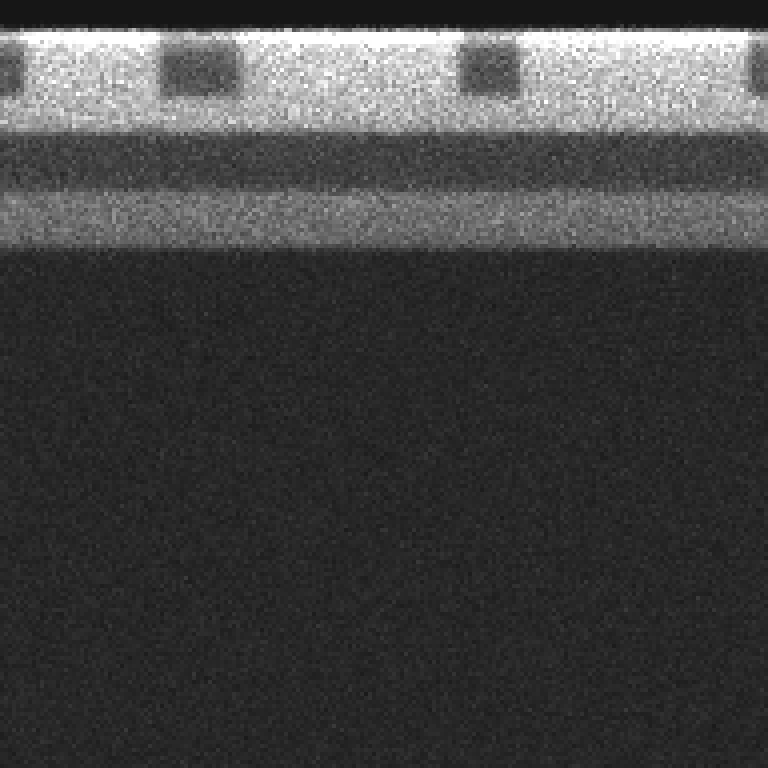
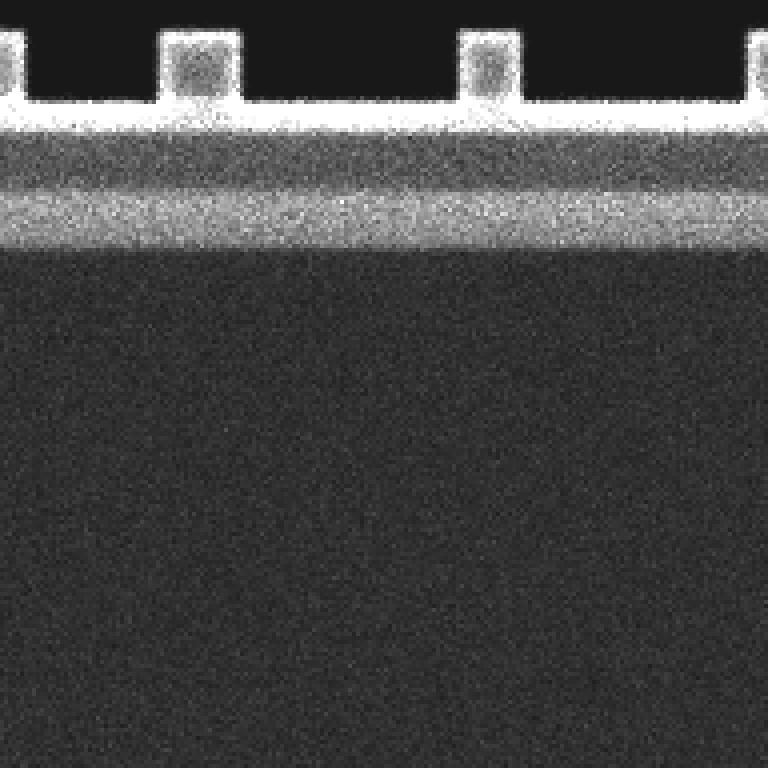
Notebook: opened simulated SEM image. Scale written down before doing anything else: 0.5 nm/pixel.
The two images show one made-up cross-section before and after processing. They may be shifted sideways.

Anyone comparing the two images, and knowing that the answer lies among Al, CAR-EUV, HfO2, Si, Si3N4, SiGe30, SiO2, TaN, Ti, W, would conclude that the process removed HfO2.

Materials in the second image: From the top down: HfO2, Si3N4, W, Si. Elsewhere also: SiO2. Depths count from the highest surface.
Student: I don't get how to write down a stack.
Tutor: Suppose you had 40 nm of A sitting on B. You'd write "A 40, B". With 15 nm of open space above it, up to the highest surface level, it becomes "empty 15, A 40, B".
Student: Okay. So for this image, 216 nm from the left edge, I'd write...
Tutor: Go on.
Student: empty 36, HfO2 14, Si3N4 30, W 28, Si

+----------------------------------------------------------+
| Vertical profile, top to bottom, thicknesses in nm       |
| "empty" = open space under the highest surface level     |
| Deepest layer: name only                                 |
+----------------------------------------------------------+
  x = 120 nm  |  empty 36, HfO2 14, Si3N4 30, W 28, Si